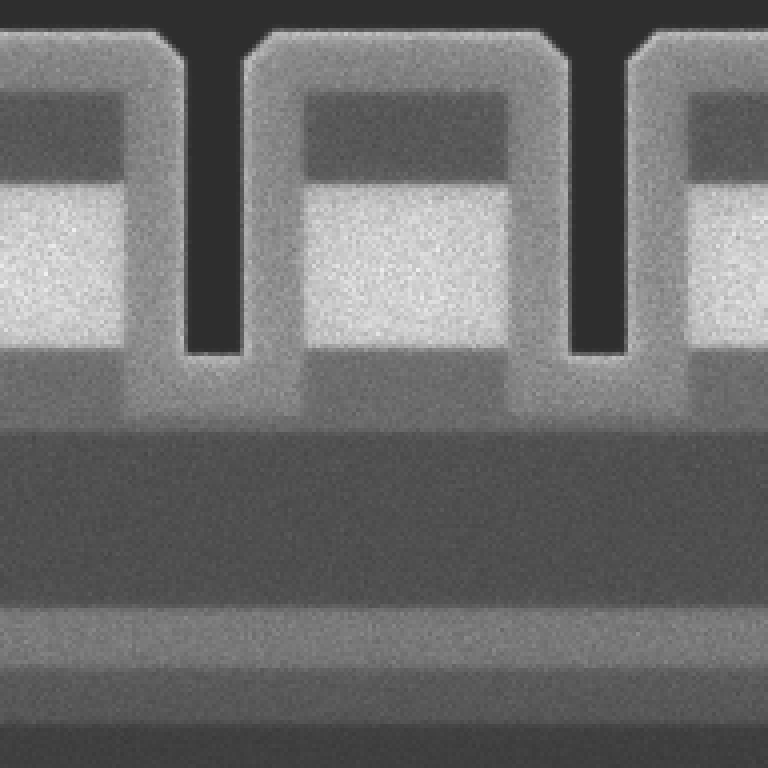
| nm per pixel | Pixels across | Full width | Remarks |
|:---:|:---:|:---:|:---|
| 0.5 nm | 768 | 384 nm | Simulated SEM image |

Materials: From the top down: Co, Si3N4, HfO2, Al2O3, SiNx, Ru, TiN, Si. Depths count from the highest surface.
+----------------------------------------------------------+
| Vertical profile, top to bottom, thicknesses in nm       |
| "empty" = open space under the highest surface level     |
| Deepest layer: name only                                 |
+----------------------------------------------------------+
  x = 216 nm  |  Co 30, Si3N4 46, HfO2 82, Al2O3 42, SiNx 88, Ru 30, TiN 28, Si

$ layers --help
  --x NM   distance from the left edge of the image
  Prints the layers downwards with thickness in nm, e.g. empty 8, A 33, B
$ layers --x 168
Co 30, Si3N4 46, HfO2 82, Al2O3 42, SiNx 88, Ru 30, TiN 28, Si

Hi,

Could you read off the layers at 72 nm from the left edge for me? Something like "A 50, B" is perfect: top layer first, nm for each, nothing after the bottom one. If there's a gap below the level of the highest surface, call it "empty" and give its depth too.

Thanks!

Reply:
Co 192, Al2O3 8, SiNx 88, Ru 30, TiN 28, Si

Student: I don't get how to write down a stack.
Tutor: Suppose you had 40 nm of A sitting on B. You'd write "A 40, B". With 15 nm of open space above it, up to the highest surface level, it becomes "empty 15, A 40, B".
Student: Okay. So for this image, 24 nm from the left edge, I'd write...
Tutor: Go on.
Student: Co 30, Si3N4 46, HfO2 82, Al2O3 42, SiNx 88, Ru 30, TiN 28, Si